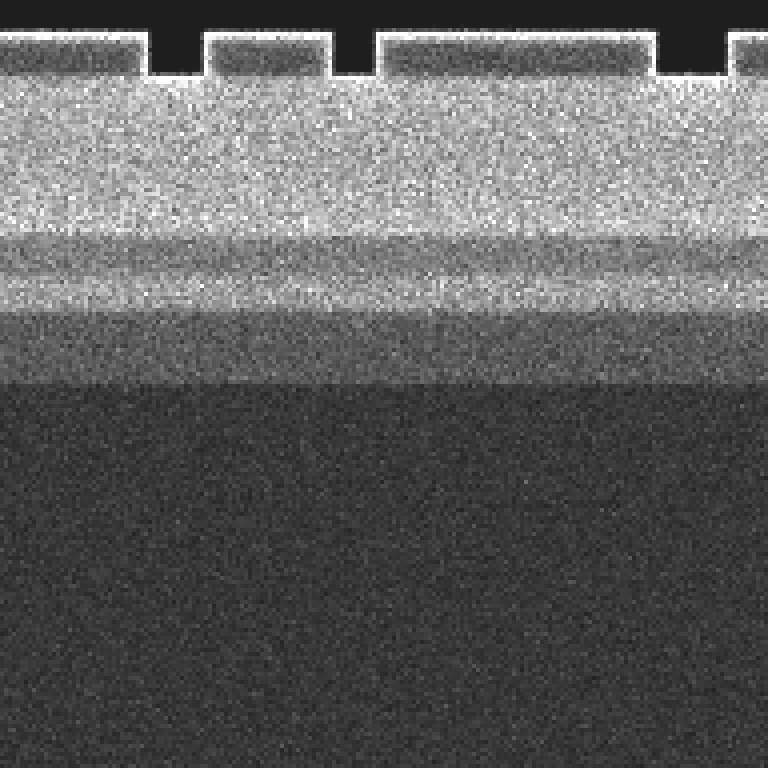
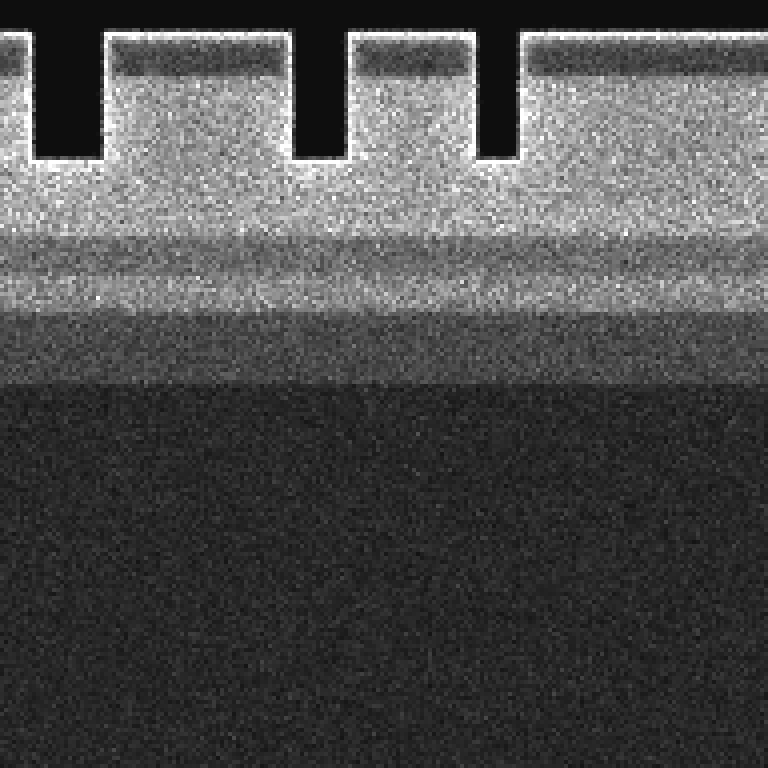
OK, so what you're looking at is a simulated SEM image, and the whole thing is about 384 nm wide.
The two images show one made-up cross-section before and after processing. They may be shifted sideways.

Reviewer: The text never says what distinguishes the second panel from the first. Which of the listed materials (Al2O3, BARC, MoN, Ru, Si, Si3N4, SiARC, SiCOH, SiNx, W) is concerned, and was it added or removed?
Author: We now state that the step removed W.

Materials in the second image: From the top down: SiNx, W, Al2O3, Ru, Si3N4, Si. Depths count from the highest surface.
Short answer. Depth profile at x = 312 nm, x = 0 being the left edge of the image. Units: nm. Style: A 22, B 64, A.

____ SiNx 22, W 80, Al2O3 20, Ru 18, Si3N4 36, Si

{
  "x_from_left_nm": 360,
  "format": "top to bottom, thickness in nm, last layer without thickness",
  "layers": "SiNx 22, W 80, Al2O3 20, Ru 18, Si3N4 36, Si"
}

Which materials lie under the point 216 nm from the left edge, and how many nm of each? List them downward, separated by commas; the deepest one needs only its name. SiNx 22, W 80, Al2O3 20, Ru 18, Si3N4 36, Si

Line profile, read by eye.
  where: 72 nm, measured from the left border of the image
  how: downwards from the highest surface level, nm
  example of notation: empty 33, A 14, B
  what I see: SiNx 22, W 80, Al2O3 20, Ru 18, Si3N4 36, Si